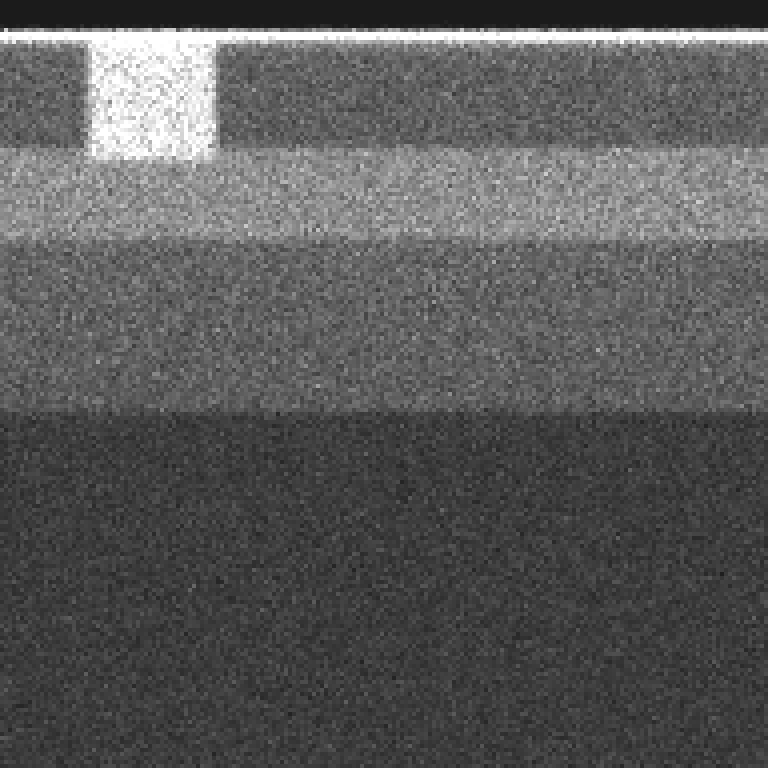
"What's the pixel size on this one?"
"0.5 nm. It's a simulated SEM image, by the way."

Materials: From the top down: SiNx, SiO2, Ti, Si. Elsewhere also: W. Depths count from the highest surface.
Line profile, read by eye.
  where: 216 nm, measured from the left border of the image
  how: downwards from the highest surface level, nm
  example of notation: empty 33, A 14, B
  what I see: SiNx 58, SiO2 46, Ti 86, Si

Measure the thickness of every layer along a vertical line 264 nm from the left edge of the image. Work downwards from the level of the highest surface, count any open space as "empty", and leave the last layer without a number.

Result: SiNx 58, SiO2 46, Ti 86, Si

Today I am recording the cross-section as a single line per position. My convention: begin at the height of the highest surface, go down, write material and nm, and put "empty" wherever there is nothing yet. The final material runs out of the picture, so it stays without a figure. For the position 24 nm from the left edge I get SiNx 58, SiO2 46, Ti 86, Si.